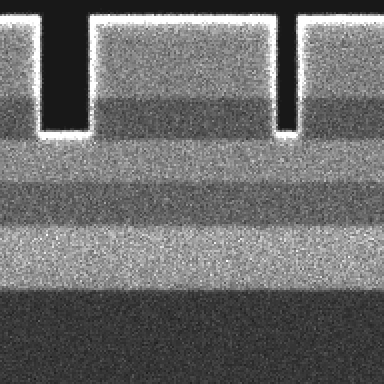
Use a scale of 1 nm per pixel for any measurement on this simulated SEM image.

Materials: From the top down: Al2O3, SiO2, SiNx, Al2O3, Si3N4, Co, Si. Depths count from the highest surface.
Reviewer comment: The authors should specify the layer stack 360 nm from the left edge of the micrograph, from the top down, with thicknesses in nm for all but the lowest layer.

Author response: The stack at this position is Al2O3 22, SiO2 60, SiNx 42, Al2O3 42, Si3N4 44, Co 64, Si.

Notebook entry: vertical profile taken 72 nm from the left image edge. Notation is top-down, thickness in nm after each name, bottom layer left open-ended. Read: empty 116, Al2O3 50, Si3N4 44, Co 64, Si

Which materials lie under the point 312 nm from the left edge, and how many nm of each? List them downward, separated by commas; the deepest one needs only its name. Al2O3 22, SiO2 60, SiNx 42, Al2O3 42, Si3N4 44, Co 64, Si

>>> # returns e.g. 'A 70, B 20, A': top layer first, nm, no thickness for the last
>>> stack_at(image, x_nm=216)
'Al2O3 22, SiO2 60, SiNx 42, Al2O3 42, Si3N4 44, Co 64, Si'